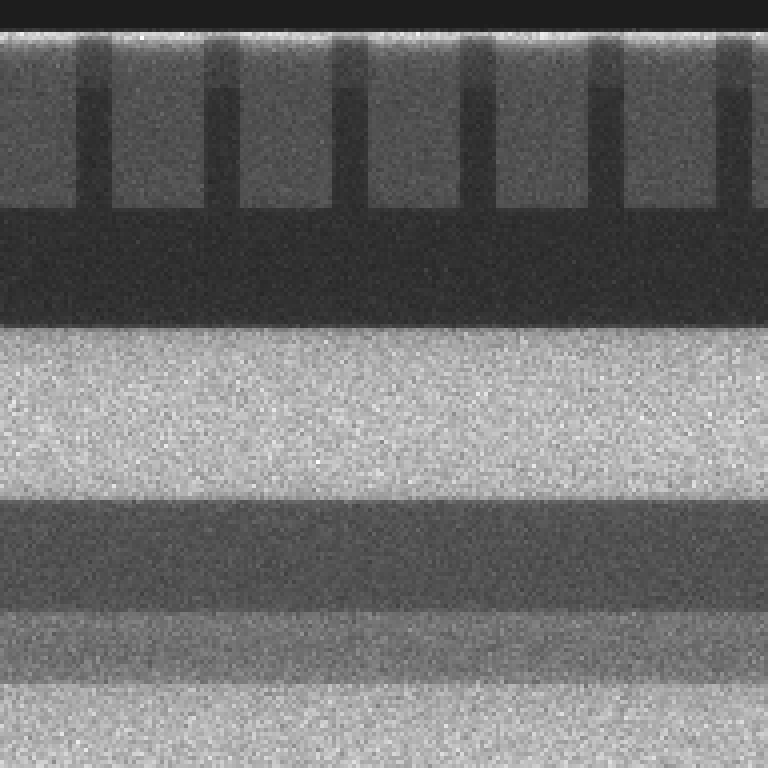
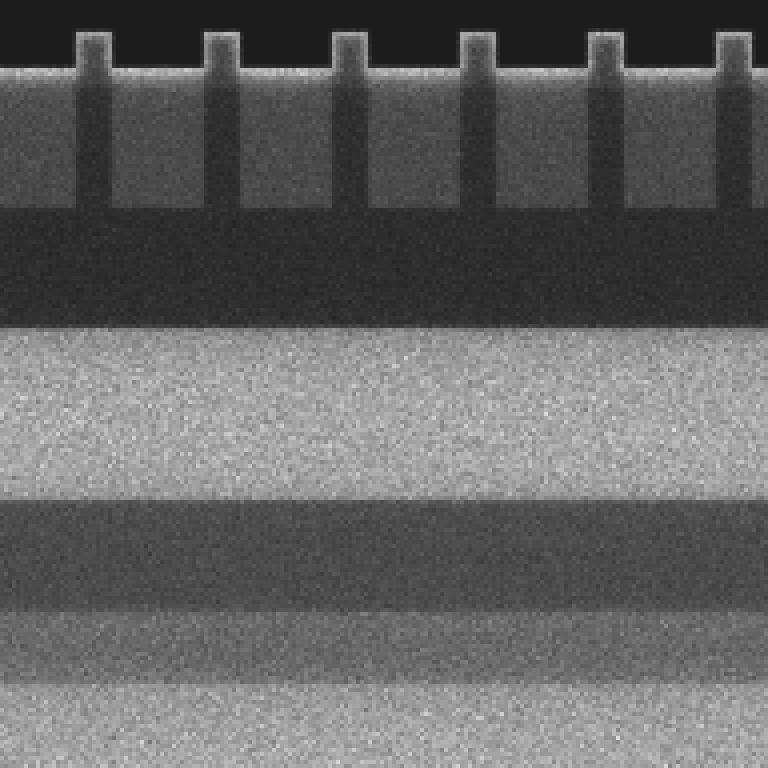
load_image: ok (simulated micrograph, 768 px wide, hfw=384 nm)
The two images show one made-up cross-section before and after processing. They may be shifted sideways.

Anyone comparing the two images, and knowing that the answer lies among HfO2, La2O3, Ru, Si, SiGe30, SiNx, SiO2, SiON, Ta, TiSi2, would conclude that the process removed SiO2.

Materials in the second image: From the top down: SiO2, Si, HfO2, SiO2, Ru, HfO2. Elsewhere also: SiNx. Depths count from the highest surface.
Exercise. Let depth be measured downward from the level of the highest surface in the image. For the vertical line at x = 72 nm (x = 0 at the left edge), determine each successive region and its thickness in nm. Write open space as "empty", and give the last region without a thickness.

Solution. empty 18, SiO2 70, Si 60, HfO2 86, SiO2 56, Ru 36, HfO2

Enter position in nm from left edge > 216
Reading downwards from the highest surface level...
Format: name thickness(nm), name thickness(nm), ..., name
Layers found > empty 18, SiO2 70, Si 60, HfO2 86, SiO2 56, Ru 36, HfO2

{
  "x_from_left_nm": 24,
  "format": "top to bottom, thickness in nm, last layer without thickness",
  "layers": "empty 18, SiO2 70, Si 60, HfO2 86, SiO2 56, Ru 36, HfO2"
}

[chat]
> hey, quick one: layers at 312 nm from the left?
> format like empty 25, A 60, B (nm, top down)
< empty 18, SiO2 70, Si 60, HfO2 86, SiO2 56, Ru 36, HfO2